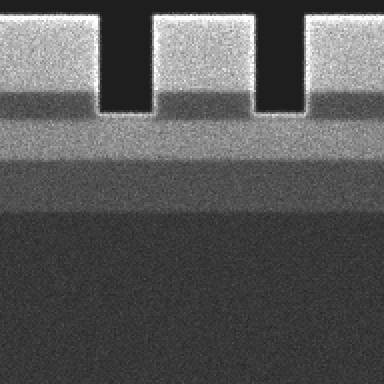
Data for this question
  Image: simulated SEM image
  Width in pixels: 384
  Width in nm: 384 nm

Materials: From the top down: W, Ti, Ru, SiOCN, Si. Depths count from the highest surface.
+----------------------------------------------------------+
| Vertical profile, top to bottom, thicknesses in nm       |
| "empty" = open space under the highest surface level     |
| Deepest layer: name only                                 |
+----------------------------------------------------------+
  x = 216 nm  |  W 76, Ti 28, Ru 40, SiOCN 52, Si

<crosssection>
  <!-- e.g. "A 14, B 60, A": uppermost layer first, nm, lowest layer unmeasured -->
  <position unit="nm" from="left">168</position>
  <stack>W 76, Ti 28, Ru 40, SiOCN 52, Si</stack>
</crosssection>